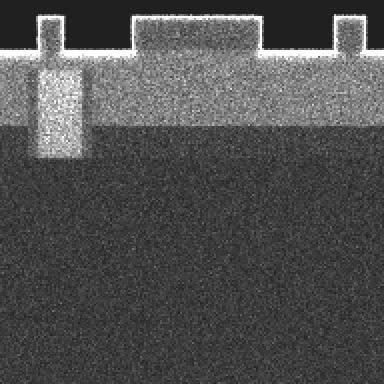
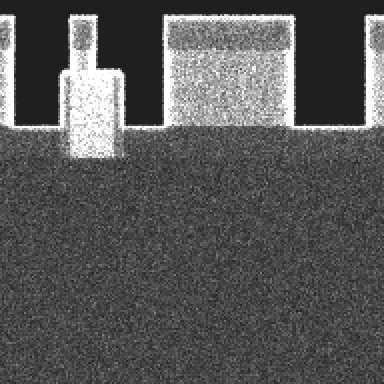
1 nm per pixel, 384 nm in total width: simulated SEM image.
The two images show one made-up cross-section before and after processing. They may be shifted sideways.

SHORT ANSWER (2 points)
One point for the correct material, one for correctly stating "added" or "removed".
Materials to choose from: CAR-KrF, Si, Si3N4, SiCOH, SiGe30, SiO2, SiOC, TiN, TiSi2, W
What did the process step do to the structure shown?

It removed SiO2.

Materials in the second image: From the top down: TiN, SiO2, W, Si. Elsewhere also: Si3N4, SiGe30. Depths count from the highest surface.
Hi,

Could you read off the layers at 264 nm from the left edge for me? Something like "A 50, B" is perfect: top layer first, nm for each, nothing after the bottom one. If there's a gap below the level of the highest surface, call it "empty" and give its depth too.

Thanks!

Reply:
TiN 34, SiO2 76, SiGe30 32, Si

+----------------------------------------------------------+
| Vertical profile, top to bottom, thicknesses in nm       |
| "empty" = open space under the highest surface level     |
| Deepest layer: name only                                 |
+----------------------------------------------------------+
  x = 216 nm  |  TiN 34, SiO2 76, SiGe30 32, Si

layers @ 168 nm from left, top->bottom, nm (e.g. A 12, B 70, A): TiN 34, SiO2 76, SiGe30 32, Si